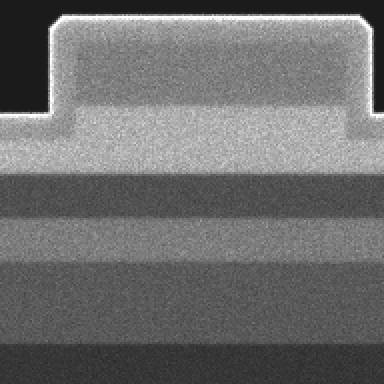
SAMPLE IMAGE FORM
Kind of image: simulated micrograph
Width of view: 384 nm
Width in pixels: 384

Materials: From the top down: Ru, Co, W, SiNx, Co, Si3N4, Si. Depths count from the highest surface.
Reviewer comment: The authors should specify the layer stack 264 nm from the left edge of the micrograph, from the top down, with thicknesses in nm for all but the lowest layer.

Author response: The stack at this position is Ru 26, Co 64, W 68, SiNx 44, Co 44, Si3N4 82, Si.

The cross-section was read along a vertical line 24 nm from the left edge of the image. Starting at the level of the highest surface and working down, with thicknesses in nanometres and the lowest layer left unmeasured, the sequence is empty 98, Ru 26, W 34, SiNx 44, Co 44, Si3N4 82, Si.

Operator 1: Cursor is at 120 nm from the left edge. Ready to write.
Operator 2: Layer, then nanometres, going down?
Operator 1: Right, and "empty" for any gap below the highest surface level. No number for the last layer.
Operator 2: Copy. Ru 26, Co 64, W 68, SiNx 44, Co 44, Si3N4 82, Si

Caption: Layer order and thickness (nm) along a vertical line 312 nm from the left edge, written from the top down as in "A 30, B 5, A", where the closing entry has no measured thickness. Ru 26, Co 64, W 68, SiNx 44, Co 44, Si3N4 82, Si